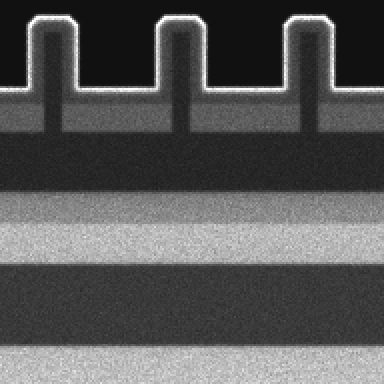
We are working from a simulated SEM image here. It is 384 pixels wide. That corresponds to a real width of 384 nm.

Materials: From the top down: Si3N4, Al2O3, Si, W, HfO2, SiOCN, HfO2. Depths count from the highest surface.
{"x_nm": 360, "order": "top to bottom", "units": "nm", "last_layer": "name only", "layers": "empty 72, Si3N4 16, Al2O3 28, Si 60, W 32, HfO2 40, SiOCN 82, HfO2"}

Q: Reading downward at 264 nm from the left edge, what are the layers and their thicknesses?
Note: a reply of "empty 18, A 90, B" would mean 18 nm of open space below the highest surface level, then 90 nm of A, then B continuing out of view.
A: empty 72, Si3N4 16, Al2O3 28, Si 60, W 32, HfO2 40, SiOCN 82, HfO2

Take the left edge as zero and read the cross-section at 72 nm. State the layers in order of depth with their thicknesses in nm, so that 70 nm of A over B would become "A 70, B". empty 4, Si3N4 84, Al2O3 28, Si 60, W 32, HfO2 40, SiOCN 82, HfO2